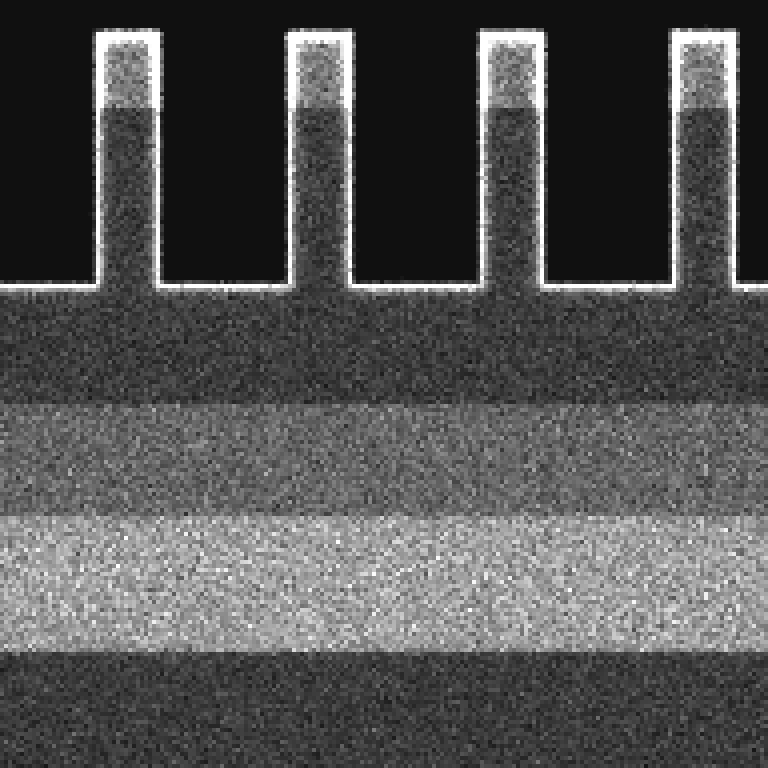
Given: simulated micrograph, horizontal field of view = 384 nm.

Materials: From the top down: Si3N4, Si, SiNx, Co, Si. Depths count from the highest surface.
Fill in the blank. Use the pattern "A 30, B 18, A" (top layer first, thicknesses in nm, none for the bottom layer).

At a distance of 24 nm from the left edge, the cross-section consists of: empty 126, Si 60, SiNx 56, Co 68, Si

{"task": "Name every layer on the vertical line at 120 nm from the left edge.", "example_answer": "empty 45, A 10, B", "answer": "empty 126, Si 60, SiNx 56, Co 68, Si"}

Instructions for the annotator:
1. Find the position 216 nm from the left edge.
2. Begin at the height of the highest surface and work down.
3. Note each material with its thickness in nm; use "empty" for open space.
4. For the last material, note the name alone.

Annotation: empty 126, Si 60, SiNx 56, Co 68, Si